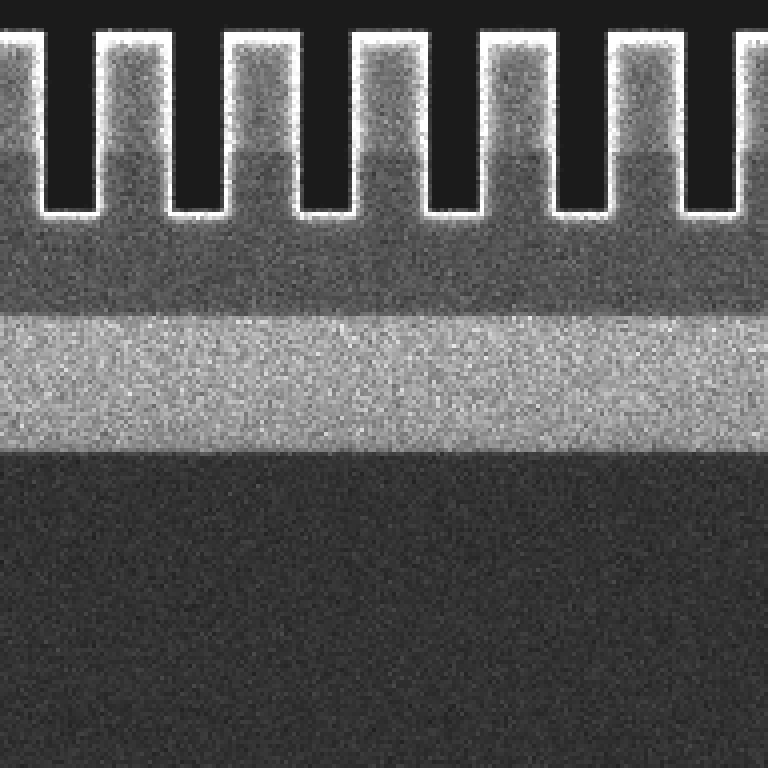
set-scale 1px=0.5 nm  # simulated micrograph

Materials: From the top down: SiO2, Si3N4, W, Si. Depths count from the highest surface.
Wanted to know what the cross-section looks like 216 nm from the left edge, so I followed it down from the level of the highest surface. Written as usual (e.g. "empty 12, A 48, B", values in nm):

empty 90, Si3N4 52, W 68, Si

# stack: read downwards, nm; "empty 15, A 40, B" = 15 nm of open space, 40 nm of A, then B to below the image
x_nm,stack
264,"SiO2 60, Si3N4 82, W 68, Si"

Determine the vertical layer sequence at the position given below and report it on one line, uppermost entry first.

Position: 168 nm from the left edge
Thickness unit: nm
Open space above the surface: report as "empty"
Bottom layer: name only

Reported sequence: empty 90, Si3N4 52, W 68, Si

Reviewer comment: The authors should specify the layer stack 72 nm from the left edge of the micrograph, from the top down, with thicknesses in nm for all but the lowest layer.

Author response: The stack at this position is SiO2 60, Si3N4 82, W 68, Si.